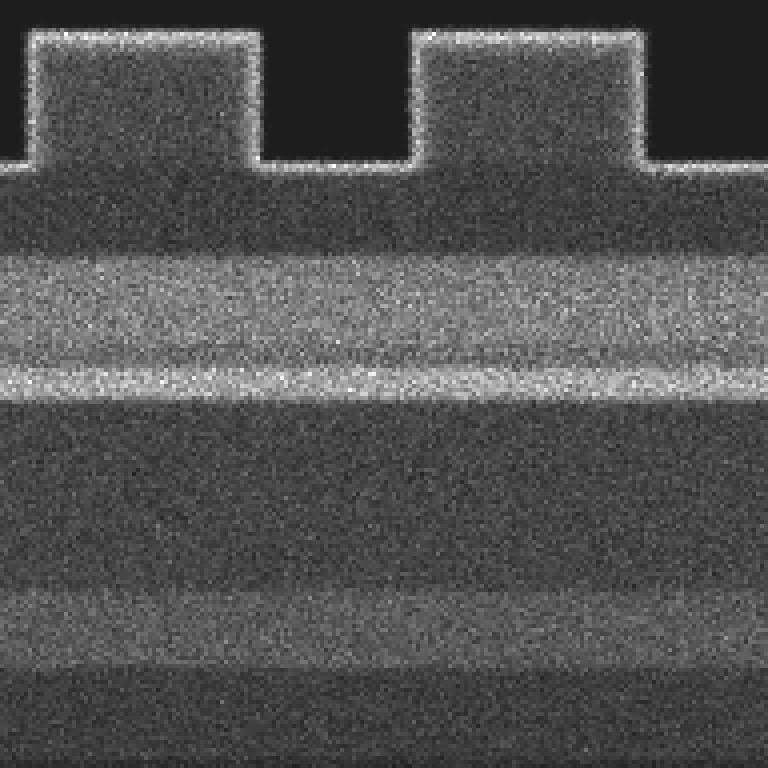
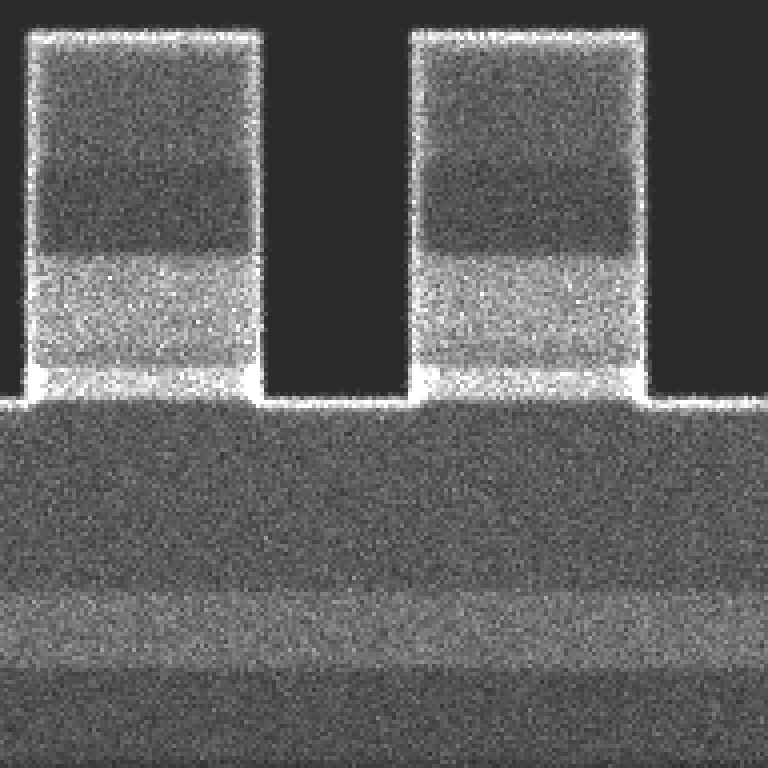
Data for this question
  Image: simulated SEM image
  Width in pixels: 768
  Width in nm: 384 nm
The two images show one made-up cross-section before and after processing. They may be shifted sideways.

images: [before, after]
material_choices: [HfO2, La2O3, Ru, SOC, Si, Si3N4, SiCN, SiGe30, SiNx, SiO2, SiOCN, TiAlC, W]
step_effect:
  removed: HfO2 and Ru and SiNx and W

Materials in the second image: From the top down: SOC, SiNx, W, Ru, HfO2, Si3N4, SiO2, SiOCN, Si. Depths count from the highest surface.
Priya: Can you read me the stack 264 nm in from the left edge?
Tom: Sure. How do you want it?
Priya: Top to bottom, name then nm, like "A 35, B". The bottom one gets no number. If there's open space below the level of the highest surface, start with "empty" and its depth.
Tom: SOC 66, SiNx 46, W 44, Ru 12, HfO2 16, Si3N4 96, SiO2 38, SiOCN 46, Si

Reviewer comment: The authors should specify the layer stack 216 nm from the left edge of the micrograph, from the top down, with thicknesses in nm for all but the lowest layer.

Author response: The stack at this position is SOC 66, SiNx 46, W 44, Ru 12, HfO2 16, Si3N4 96, SiO2 38, SiOCN 46, Si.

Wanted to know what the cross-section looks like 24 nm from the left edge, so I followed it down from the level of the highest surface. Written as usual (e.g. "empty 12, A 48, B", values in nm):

SOC 66, SiNx 46, W 44, Ru 12, HfO2 16, Si3N4 96, SiO2 38, SiOCN 46, Si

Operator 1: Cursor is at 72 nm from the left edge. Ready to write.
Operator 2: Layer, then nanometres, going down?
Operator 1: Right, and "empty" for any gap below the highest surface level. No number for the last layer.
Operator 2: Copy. SOC 66, SiNx 46, W 44, Ru 12, HfO2 16, Si3N4 96, SiO2 38, SiOCN 46, Si